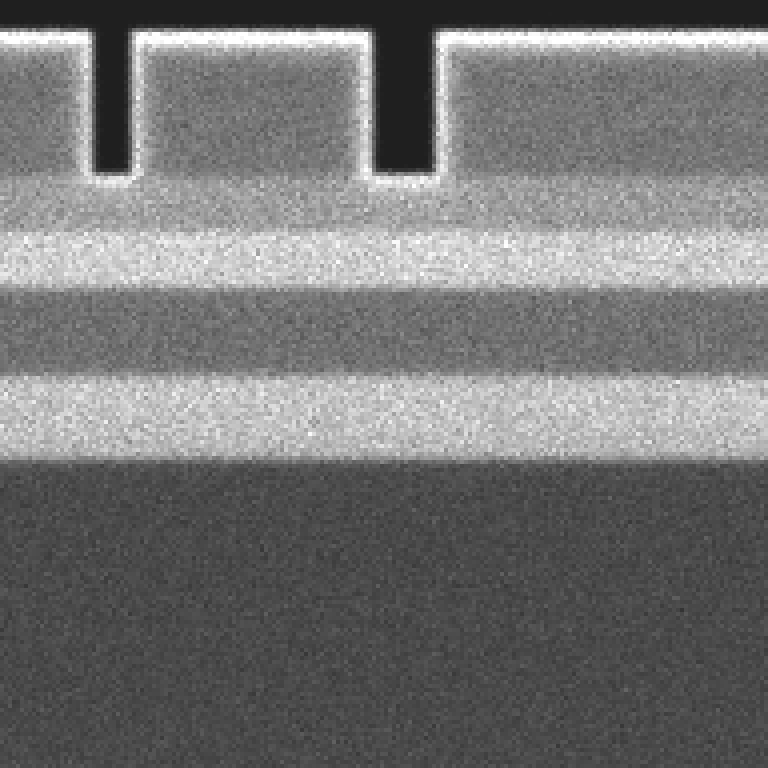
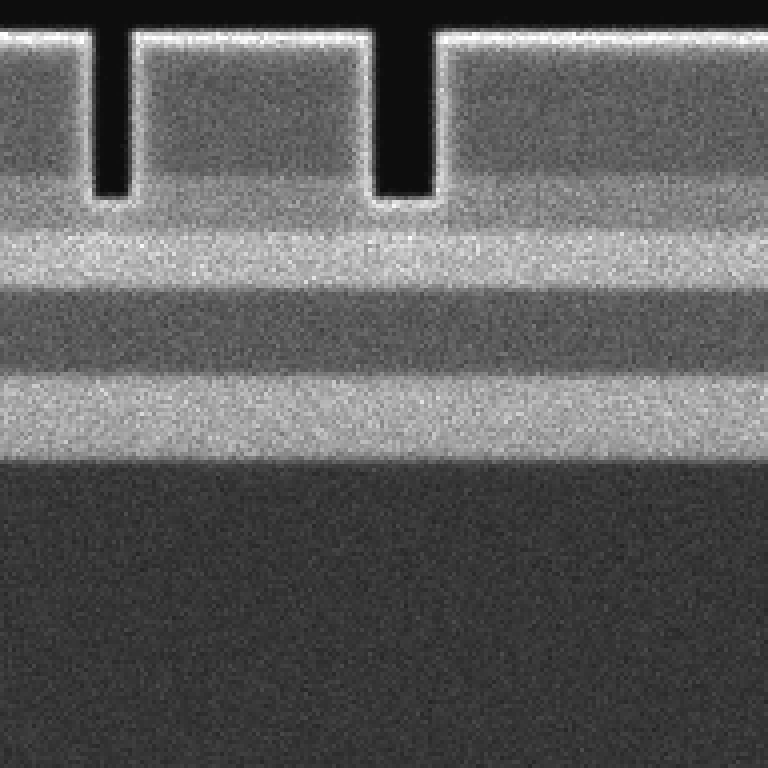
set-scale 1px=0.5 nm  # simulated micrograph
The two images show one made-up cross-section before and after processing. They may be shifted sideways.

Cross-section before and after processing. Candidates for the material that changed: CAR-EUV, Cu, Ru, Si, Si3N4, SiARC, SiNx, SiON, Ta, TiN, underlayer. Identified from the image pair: TiN (removed).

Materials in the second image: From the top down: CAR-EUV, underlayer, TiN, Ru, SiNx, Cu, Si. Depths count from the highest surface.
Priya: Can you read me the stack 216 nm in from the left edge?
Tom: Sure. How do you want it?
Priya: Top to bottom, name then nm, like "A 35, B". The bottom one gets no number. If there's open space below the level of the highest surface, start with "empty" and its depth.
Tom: empty 84, TiN 16, Ru 28, SiNx 44, Cu 42, Si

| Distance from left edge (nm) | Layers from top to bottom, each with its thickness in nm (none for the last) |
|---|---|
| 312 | CAR-EUV 34, underlayer 38, TiN 28, Ru 28, SiNx 44, Cu 42, Si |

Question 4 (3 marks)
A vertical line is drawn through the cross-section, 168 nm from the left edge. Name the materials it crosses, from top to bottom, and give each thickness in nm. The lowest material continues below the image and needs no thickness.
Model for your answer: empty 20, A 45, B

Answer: CAR-EUV 34, underlayer 38, TiN 28, Ru 28, SiNx 44, Cu 42, Si